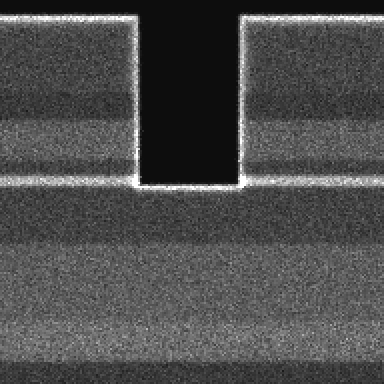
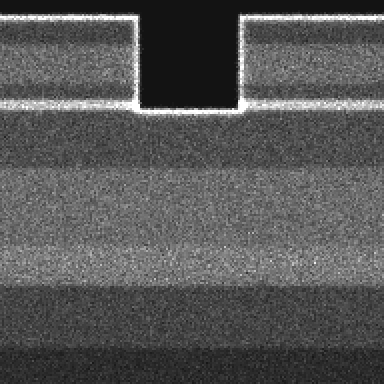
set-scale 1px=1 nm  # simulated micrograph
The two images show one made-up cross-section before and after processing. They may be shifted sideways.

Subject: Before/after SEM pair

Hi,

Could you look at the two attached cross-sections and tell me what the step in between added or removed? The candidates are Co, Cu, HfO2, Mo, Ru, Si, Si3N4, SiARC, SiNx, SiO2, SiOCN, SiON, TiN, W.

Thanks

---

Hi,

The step removed SiARC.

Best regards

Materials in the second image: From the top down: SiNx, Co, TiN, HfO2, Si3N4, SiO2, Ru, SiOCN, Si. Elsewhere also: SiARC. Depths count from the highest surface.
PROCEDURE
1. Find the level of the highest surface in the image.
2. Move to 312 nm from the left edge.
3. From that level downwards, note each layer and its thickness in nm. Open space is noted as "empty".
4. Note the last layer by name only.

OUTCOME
SiNx 28, Co 40, TiN 16, HfO2 10, Si3N4 58, SiO2 78, Ru 40, SiOCN 62, Si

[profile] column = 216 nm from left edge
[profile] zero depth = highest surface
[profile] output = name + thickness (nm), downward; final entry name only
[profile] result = empty 94, Si3N4 58, SiO2 78, Ru 40, SiOCN 62, Si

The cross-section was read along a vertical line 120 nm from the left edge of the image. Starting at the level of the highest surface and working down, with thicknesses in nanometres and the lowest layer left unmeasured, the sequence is SiNx 28, Co 40, TiN 16, HfO2 10, Si3N4 58, SiO2 78, Ru 40, SiOCN 62, Si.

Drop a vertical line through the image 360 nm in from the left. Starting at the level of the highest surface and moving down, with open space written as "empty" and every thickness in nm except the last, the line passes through SiNx 28, Co 40, TiN 16, HfO2 10, Si3N4 58, SiO2 78, Ru 40, SiOCN 62, Si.